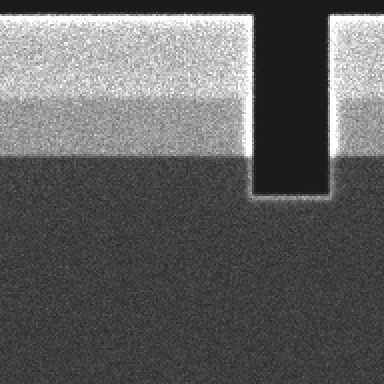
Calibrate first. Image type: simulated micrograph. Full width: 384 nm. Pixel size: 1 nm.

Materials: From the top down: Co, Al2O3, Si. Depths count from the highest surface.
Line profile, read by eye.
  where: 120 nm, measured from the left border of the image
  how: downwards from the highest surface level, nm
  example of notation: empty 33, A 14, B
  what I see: Co 82, Al2O3 58, Si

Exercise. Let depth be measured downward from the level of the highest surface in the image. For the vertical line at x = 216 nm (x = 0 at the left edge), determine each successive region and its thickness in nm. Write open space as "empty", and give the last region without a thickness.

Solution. Co 82, Al2O3 58, Si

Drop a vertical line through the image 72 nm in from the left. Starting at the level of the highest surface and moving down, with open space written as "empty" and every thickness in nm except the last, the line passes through Co 82, Al2O3 58, Si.